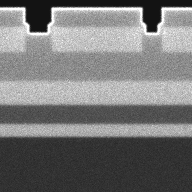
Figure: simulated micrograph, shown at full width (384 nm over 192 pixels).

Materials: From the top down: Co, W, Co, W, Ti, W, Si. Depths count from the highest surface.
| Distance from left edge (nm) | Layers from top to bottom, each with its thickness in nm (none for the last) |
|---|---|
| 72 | empty 50, Co 96, W 48, Ti 38, W 26, Si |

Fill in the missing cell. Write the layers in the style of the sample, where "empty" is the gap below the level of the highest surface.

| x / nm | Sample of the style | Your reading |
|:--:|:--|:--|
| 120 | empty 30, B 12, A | Co 38, W 50, Co 58, W 48, Ti 38, W 26, Si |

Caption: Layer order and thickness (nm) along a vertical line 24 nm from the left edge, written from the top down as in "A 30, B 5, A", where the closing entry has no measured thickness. Co 38, W 50, Co 58, W 48, Ti 38, W 26, Si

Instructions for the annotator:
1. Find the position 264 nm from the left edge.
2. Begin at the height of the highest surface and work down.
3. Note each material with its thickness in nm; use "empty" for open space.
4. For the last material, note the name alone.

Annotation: Co 38, W 50, Co 58, W 48, Ti 38, W 26, Si